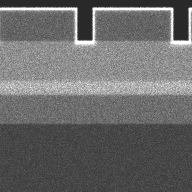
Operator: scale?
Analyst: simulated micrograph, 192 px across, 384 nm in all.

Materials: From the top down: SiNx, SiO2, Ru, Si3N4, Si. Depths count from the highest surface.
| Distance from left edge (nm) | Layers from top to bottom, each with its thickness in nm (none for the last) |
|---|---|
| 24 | SiNx 66, SiO2 80, Ru 28, Si3N4 58, Si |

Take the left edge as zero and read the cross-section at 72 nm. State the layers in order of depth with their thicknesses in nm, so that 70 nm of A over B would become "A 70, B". SiNx 66, SiO2 80, Ru 28, Si3N4 58, Si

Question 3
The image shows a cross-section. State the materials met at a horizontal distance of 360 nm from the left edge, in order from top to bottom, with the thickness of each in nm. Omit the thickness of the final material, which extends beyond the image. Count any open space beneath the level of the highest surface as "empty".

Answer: empty 66, SiO2 80, Ru 28, Si3N4 58, Si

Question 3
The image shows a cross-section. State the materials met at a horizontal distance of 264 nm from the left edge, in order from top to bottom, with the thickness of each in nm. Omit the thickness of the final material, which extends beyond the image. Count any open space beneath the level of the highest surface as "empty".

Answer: SiNx 66, SiO2 80, Ru 28, Si3N4 58, Si